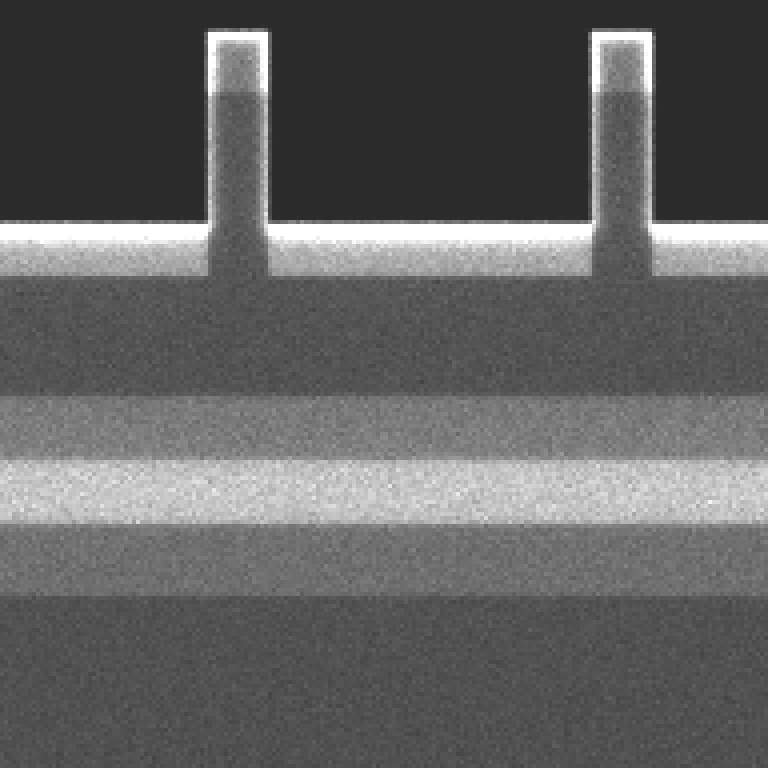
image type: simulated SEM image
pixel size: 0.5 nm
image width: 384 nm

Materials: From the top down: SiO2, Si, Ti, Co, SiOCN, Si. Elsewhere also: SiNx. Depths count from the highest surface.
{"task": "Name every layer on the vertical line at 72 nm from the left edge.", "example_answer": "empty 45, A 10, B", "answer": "empty 96, SiO2 26, Si 60, Ti 32, Co 32, SiOCN 36, Si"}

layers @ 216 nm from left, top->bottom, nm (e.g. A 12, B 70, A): empty 96, SiO2 26, Si 60, Ti 32, Co 32, SiOCN 36, Si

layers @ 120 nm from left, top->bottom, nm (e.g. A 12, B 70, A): SiNx 30, Si 152, Ti 32, Co 32, SiOCN 36, Si